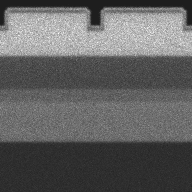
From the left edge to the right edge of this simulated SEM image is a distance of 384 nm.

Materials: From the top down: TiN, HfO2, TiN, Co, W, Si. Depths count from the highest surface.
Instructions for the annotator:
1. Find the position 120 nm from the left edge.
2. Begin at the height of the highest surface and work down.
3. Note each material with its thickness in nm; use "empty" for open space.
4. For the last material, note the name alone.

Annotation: TiN 10, HfO2 86, TiN 66, Co 26, W 80, Si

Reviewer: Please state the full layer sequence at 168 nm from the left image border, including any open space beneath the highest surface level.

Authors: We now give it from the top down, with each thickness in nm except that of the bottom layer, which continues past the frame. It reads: TiN 10, HfO2 86, TiN 66, Co 26, W 80, Si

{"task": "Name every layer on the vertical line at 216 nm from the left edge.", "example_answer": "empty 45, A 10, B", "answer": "TiN 10, HfO2 86, TiN 66, Co 26, W 80, Si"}